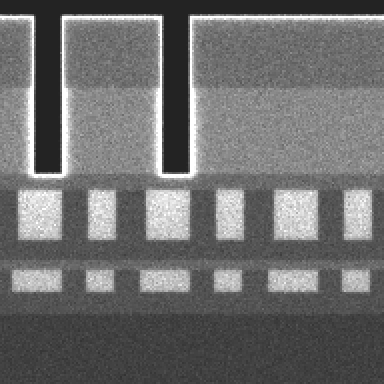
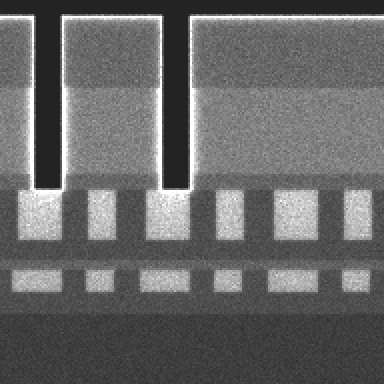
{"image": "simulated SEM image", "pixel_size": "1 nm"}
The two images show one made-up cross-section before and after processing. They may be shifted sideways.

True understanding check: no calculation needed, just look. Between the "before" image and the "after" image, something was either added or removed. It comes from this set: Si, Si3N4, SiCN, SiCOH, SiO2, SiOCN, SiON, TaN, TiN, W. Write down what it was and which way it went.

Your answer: Si3N4 (removed)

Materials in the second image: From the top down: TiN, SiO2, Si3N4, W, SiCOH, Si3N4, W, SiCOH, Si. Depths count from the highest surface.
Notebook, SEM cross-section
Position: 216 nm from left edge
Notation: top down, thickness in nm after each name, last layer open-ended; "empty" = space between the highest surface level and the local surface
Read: TiN 72, SiO2 86, Si3N4 16, W 50, SiCOH 20, Si3N4 10, W 22, SiCOH 22, Si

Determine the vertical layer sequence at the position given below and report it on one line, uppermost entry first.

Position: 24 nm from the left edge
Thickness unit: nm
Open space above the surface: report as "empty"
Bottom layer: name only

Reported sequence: TiN 72, SiO2 86, Si3N4 16, W 50, SiCOH 20, Si3N4 10, W 22, SiCOH 22, Si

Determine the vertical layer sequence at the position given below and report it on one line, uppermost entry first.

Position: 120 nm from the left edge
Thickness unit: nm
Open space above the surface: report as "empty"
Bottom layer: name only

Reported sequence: TiN 72, SiO2 86, Si3N4 16, SiCOH 70, Si3N4 10, SiCOH 44, Si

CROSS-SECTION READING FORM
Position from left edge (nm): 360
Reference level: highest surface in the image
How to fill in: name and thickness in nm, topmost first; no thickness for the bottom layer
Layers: TiN 72, SiO2 86, Si3N4 16, W 50, SiCOH 20, Si3N4 10, W 22, SiCOH 22, Si